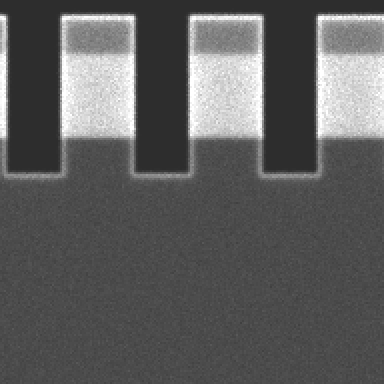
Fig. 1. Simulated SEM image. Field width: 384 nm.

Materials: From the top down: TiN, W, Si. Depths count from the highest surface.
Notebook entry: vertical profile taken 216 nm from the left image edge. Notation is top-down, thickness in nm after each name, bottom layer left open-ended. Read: TiN 38, W 84, Si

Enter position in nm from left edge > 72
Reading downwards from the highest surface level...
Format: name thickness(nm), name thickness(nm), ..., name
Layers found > TiN 38, W 84, Si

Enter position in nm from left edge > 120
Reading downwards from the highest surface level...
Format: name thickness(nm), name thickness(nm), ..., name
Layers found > TiN 38, W 84, Si